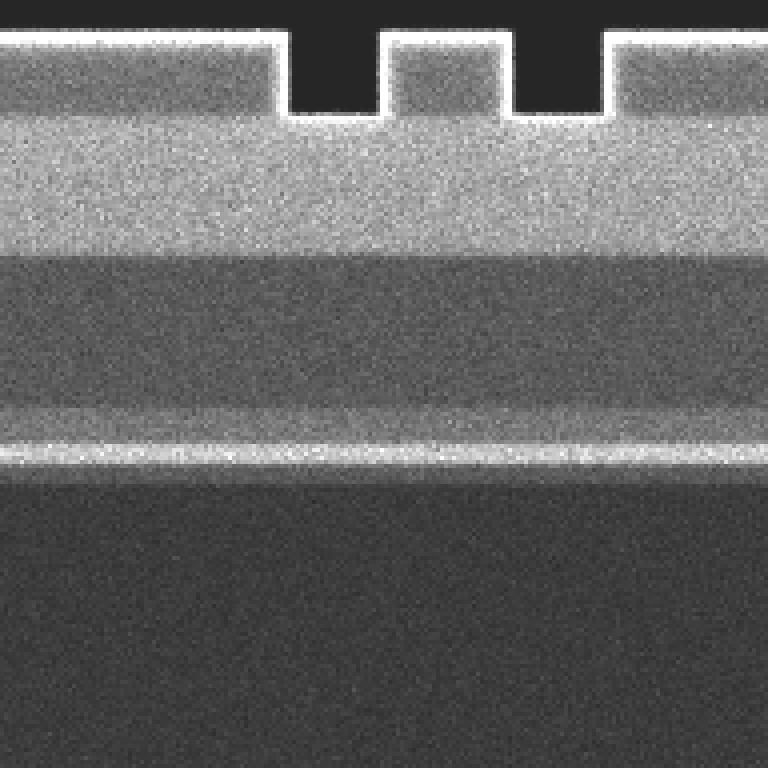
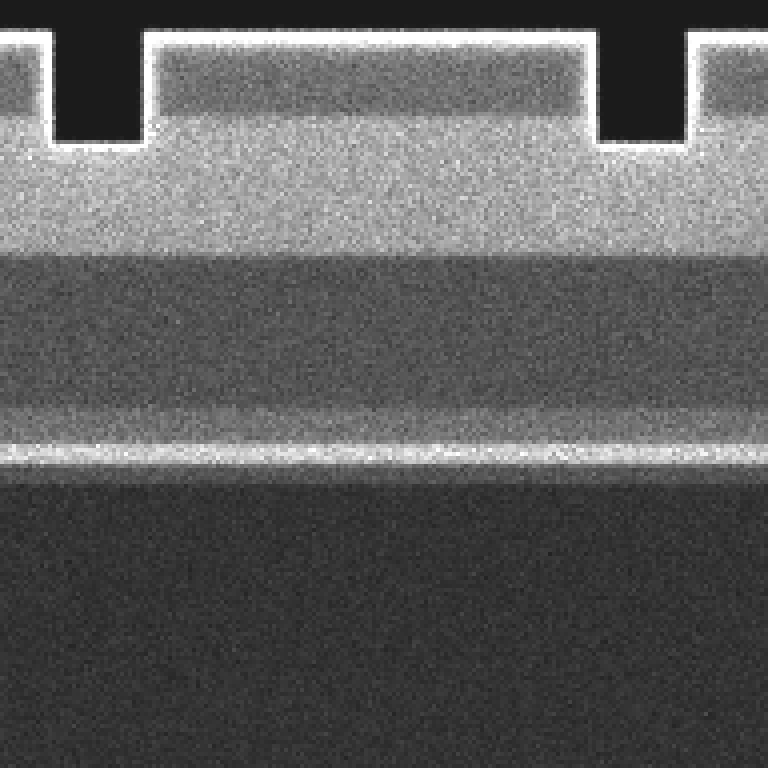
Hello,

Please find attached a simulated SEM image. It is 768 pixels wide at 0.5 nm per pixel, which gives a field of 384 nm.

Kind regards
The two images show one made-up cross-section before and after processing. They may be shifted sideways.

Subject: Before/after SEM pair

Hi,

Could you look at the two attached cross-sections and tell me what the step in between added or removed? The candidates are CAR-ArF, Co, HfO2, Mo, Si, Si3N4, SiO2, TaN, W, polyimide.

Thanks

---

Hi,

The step removed W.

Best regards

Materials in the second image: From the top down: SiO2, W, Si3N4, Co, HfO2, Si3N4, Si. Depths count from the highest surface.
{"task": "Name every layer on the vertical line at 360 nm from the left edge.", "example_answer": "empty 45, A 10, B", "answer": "SiO2 42, W 70, Si3N4 76, Co 18, HfO2 10, Si3N4 10, Si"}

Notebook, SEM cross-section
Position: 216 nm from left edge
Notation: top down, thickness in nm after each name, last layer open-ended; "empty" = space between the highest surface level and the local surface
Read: SiO2 42, W 70, Si3N4 76, Co 18, HfO2 10, Si3N4 10, Si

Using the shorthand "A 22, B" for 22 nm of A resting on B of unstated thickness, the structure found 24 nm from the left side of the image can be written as SiO2 42, W 70, Si3N4 76, Co 18, HfO2 10, Si3N4 10, Si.